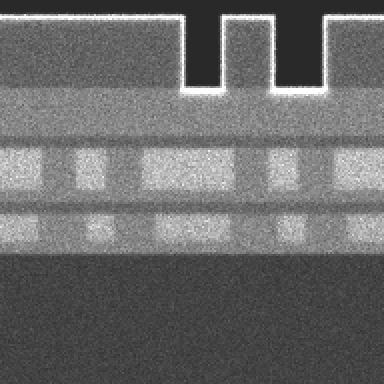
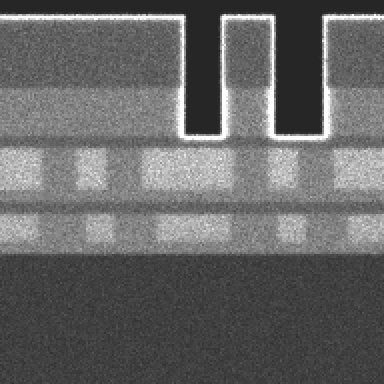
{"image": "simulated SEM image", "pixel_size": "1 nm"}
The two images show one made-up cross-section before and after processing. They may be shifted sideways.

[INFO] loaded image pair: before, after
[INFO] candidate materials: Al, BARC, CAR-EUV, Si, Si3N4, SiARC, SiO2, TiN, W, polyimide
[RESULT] removed SiO2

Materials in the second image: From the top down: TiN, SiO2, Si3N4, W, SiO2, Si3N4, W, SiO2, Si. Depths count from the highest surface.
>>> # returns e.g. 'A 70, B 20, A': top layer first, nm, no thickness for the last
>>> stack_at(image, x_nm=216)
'empty 120, Si3N4 12, W 42, SiO2 12, Si3N4 12, W 28, SiO2 12, Si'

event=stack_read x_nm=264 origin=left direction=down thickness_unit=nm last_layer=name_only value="TiN 72, SiO2 48, Si3N4 12, SiO2 54, Si3N4 12, SiO2 40, Si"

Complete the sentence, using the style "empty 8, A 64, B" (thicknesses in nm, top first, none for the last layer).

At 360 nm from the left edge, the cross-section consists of TiN 72, SiO2 48, Si3N4 12, W 42, SiO2 12, Si3N4 12, W 28, SiO2 12, Si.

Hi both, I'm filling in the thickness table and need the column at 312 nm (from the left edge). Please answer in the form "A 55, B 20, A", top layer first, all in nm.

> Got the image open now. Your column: empty 120, Si3N4 12, SiO2 54, Si3N4 12, SiO2 40, Si